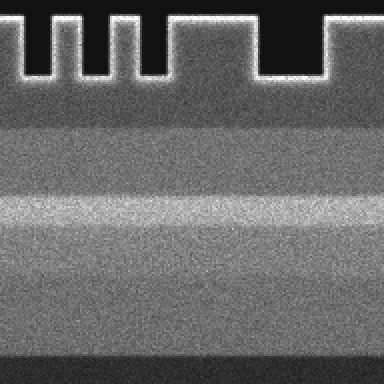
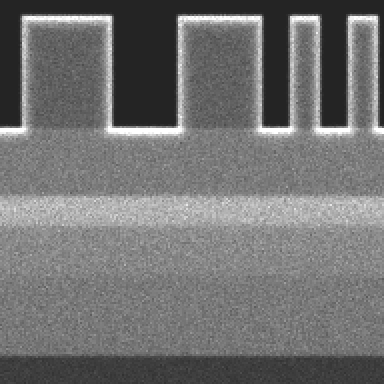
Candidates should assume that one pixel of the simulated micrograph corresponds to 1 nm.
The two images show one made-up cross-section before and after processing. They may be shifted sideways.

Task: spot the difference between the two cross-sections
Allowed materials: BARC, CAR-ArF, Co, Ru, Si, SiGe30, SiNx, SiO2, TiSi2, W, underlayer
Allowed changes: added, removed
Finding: removed underlayer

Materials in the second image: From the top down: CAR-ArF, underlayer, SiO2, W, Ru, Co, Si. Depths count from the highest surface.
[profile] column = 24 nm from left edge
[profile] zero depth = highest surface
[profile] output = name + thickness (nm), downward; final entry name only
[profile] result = CAR-ArF 60, underlayer 52, SiO2 68, W 30, Ru 50, Co 80, Si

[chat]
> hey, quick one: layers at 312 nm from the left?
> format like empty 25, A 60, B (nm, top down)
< CAR-ArF 60, underlayer 52, SiO2 68, W 30, Ru 50, Co 80, Si